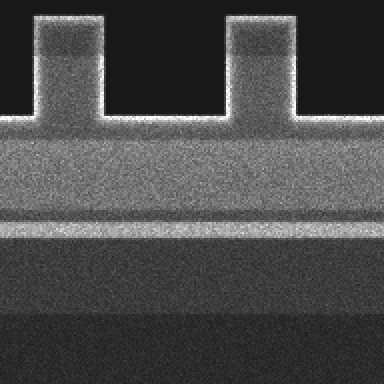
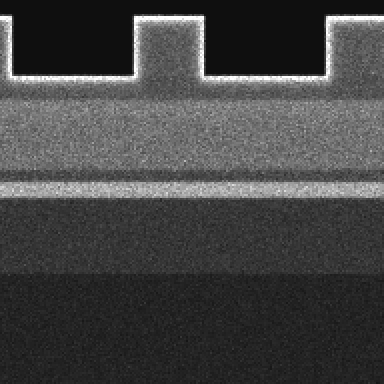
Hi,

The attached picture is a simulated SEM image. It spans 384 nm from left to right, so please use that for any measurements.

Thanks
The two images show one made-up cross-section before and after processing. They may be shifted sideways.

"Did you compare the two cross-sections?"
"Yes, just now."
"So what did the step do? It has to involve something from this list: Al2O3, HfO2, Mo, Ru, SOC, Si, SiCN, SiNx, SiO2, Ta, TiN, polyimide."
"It removed SOC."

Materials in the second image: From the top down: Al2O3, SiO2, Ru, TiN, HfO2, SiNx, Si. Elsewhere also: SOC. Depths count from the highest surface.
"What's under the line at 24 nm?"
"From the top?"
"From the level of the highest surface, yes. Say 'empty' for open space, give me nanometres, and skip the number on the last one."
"empty 60, SiO2 24, Ru 70, TiN 12, HfO2 16, SiNx 76, Si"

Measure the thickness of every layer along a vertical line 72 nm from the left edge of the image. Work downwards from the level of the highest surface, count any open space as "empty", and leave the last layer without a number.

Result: empty 60, SiO2 24, Ru 70, TiN 12, HfO2 16, SiNx 76, Si